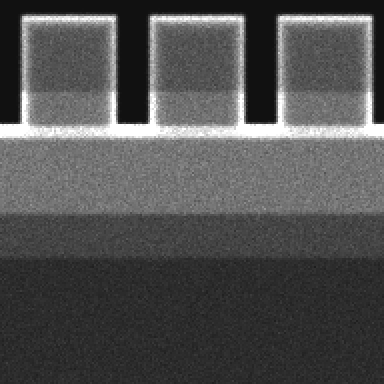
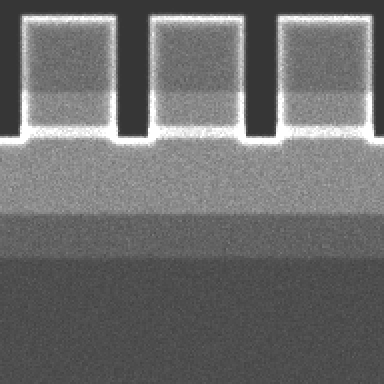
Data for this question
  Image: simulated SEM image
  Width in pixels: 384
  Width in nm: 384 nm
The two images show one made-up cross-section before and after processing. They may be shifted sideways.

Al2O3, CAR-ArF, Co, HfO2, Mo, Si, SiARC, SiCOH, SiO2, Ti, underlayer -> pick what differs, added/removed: HfO2 removed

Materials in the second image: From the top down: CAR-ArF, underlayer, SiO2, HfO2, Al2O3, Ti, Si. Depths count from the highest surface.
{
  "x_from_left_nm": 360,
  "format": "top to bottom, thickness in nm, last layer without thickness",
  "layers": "CAR-ArF 46, underlayer 30, SiO2 34, HfO2 12, Al2O3 76, Ti 44, Si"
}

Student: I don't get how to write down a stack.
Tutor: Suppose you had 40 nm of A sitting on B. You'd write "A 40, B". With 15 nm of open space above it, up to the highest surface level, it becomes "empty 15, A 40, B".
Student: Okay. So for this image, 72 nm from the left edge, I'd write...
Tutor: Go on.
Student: CAR-ArF 46, underlayer 30, SiO2 34, HfO2 12, Al2O3 76, Ti 44, Si